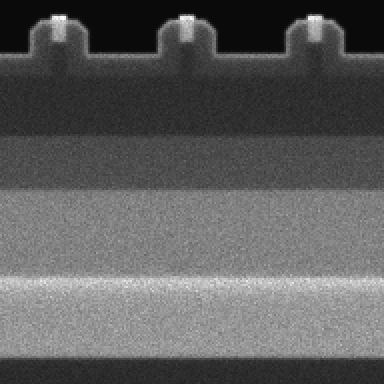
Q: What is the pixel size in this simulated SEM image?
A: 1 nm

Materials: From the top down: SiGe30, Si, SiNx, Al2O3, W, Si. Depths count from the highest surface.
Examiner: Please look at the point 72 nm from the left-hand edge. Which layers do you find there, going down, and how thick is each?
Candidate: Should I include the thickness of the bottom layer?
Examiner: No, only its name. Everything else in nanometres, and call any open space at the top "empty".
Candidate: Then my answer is empty 4, SiGe30 56, Si 60, SiNx 54, Al2O3 88, W 80, Si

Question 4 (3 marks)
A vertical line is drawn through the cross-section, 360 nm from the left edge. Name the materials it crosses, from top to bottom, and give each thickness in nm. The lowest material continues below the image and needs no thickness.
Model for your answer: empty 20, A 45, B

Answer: empty 38, SiGe30 22, Si 60, SiNx 54, Al2O3 88, W 80, Si